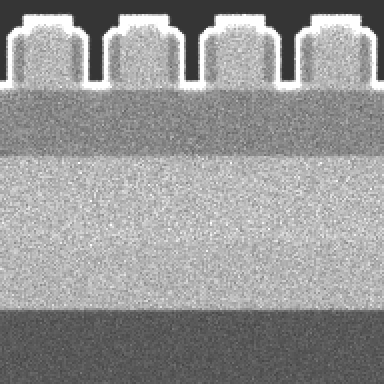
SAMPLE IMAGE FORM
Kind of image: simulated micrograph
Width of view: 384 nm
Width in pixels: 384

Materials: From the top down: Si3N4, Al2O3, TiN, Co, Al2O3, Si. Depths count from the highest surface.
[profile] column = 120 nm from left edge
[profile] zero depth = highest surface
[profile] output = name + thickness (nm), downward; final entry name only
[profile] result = Al2O3 74, TiN 66, Co 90, Al2O3 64, Si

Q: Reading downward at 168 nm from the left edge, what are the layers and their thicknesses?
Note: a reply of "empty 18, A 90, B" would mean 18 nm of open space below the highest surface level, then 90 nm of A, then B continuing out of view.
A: empty 12, Si3N4 54, Al2O3 8, TiN 66, Co 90, Al2O3 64, Si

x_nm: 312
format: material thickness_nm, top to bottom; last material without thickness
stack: Al2O3 74, TiN 66, Co 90, Al2O3 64, Si